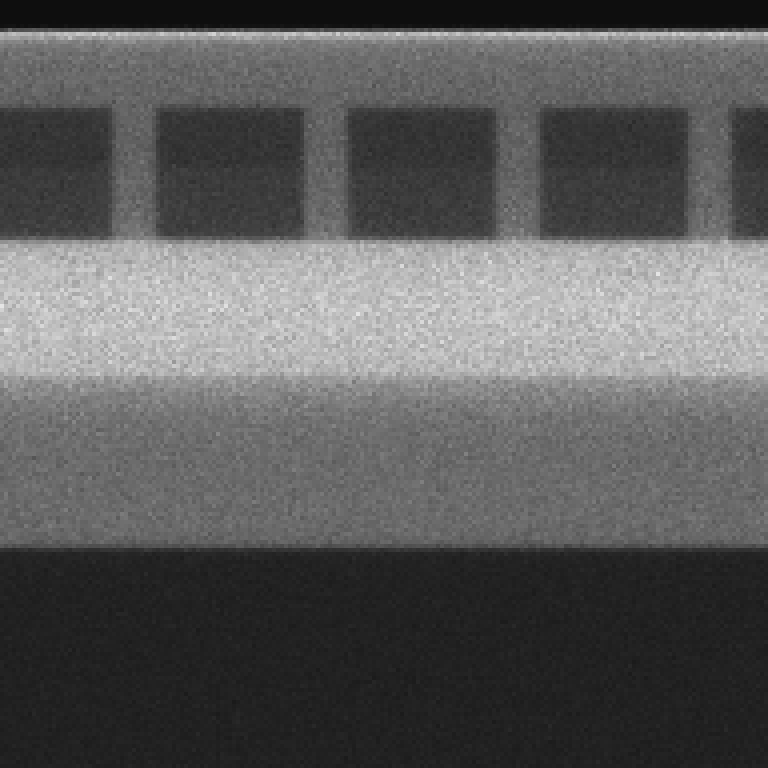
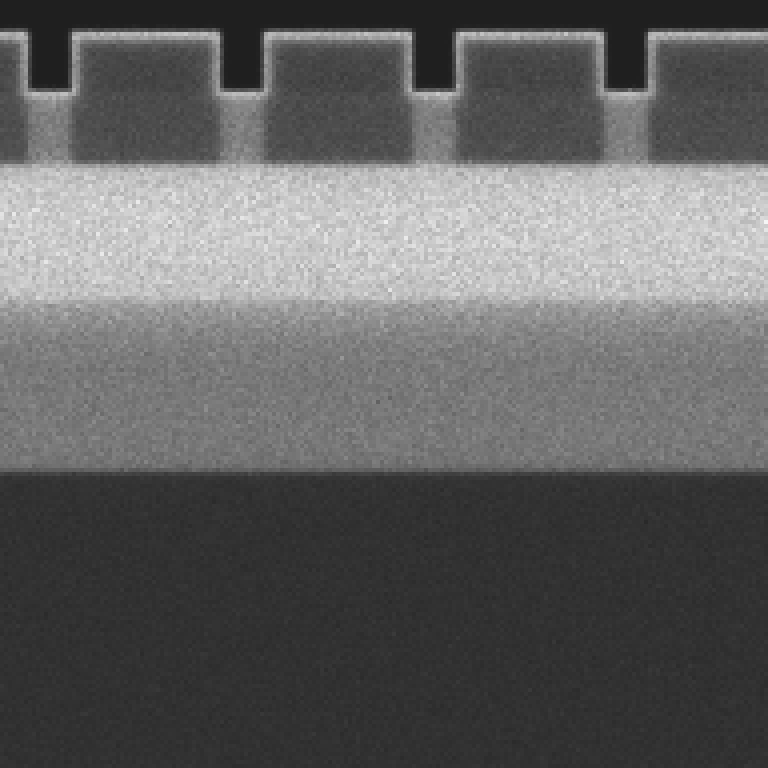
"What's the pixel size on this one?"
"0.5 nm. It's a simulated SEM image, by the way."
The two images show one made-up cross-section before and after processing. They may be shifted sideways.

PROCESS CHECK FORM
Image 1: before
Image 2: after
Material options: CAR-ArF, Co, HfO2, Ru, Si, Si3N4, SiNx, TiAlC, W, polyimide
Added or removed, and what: removed, Co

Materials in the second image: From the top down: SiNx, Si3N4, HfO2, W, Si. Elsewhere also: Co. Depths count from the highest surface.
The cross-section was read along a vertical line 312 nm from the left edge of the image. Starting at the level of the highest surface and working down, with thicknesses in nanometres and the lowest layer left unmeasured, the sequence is empty 30, Co 36, HfO2 68, W 86, Si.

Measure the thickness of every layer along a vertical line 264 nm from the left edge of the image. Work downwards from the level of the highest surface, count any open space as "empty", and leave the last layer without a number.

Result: SiNx 30, Si3N4 36, HfO2 68, W 86, Si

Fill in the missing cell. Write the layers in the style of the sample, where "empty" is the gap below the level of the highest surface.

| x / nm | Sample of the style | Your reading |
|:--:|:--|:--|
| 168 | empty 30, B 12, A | SiNx 30, Si3N4 36, HfO2 68, W 86, Si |